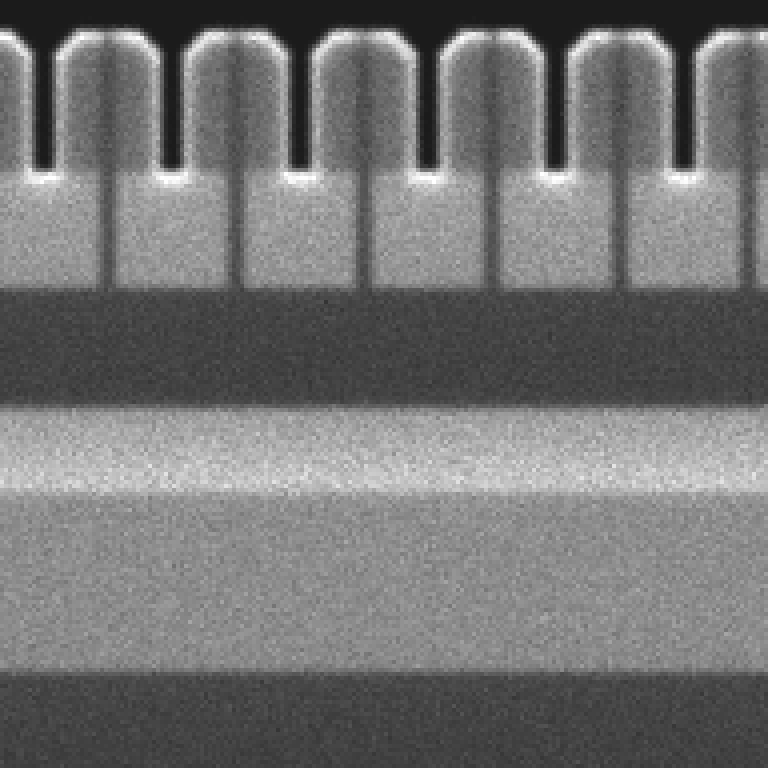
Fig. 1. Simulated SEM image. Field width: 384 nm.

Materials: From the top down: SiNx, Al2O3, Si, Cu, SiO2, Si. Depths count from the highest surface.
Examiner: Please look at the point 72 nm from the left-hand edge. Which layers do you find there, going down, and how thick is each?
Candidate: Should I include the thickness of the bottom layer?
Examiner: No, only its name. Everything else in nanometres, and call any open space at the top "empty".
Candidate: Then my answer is empty 4, SiNx 66, Al2O3 58, Si 60, Cu 42, SiO2 90, Si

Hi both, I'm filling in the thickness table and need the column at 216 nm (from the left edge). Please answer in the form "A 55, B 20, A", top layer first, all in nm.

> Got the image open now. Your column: empty 70, Al2O3 58, Si 60, Cu 42, SiO2 90, Si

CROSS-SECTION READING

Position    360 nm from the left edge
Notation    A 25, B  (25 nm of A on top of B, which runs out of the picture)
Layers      SiNx 70, Al2O3 58, Si 60, Cu 42, SiO2 90, Si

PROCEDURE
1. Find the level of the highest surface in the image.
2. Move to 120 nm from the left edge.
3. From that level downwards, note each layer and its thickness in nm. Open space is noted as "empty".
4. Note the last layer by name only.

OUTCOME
Si 188, Cu 42, SiO2 90, Si